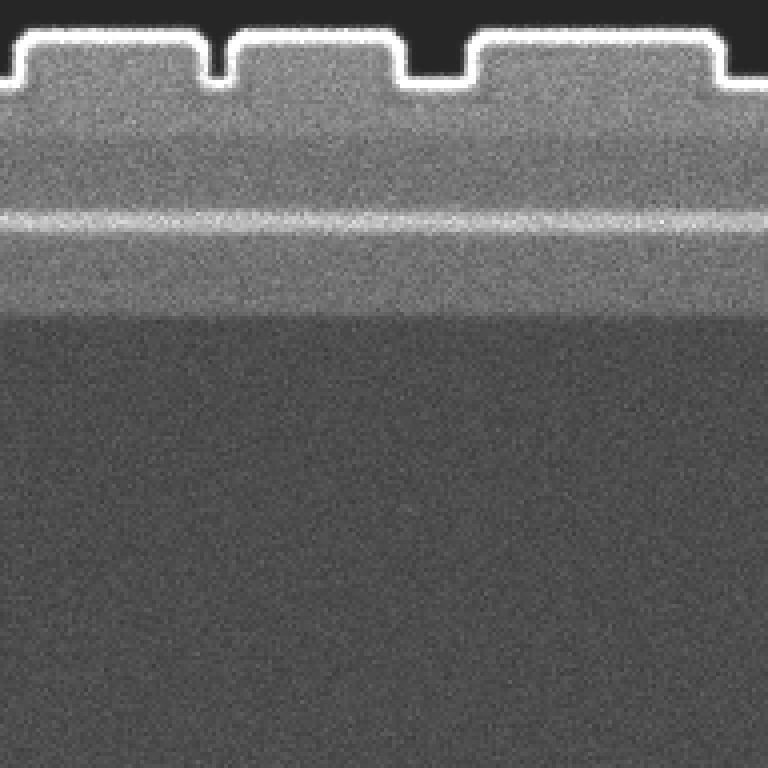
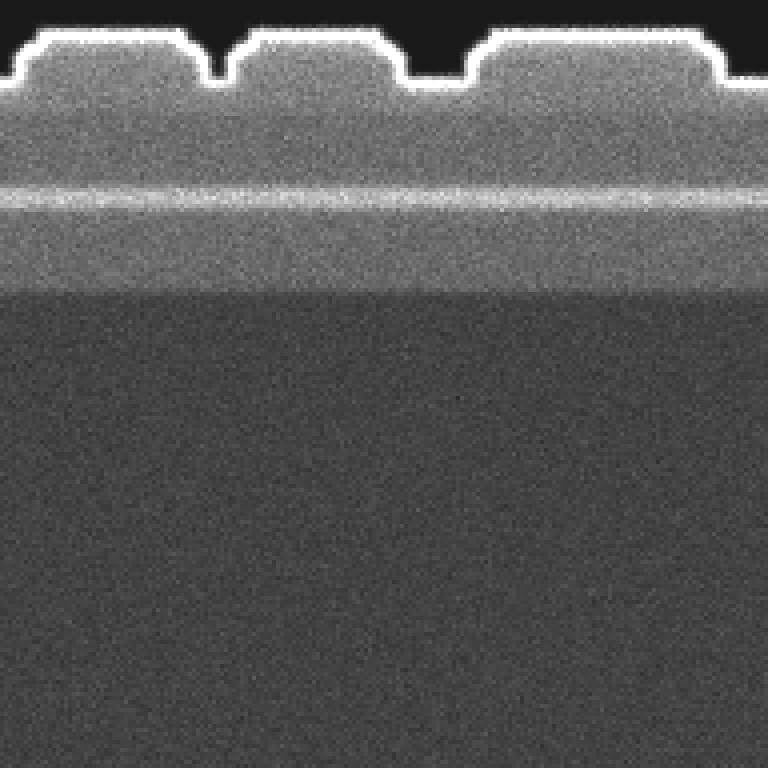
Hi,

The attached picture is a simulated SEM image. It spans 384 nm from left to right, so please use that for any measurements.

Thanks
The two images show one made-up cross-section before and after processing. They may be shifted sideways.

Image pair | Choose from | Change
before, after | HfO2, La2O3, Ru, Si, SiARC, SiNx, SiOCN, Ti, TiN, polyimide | SiNx (removed)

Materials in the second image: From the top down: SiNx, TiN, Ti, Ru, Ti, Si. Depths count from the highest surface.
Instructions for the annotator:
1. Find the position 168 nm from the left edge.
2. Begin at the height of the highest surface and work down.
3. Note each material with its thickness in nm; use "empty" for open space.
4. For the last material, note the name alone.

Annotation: TiN 40, Ti 38, Ru 10, Ti 42, Si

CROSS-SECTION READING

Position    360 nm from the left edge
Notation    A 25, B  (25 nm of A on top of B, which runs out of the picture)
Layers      empty 12, SiNx 12, TiN 16, Ti 38, Ru 10, Ti 42, Si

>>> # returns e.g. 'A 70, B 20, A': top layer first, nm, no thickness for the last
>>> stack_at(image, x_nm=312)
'TiN 40, Ti 38, Ru 10, Ti 42, Si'